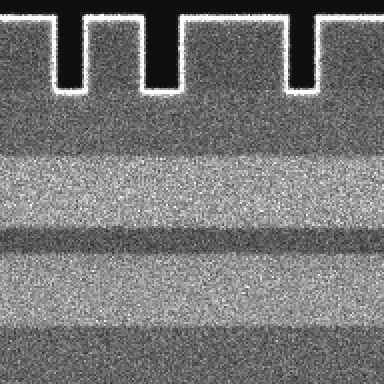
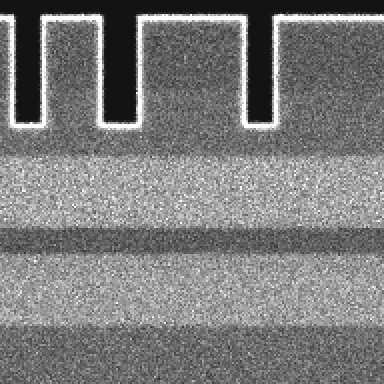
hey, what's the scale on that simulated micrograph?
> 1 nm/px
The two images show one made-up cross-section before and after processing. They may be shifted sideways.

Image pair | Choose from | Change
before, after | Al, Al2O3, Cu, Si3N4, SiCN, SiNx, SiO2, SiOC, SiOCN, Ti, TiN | Si3N4 (removed)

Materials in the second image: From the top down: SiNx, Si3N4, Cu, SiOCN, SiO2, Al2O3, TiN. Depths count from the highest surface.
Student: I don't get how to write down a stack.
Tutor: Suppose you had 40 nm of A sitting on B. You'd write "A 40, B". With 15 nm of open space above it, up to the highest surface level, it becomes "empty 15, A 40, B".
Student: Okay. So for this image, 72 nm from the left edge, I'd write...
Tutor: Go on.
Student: SiNx 74, Si3N4 66, Cu 72, SiOCN 26, SiO2 18, Al2O3 54, TiN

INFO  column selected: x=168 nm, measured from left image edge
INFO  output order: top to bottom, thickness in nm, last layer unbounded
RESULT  SiNx 74, Si3N4 66, Cu 72, SiOCN 26, SiO2 18, Al2O3 54, TiN